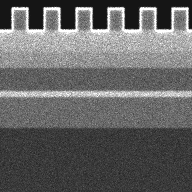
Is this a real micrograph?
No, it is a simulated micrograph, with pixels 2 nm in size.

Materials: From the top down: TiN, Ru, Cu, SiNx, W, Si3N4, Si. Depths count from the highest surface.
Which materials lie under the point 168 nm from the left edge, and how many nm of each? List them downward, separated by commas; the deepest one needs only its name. TiN 44, Ru 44, Cu 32, SiNx 46, W 12, Si3N4 62, Si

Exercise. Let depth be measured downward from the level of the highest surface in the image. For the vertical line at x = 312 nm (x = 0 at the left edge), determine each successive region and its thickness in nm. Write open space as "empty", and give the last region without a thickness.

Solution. empty 44, Ru 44, Cu 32, SiNx 46, W 12, Si3N4 62, Si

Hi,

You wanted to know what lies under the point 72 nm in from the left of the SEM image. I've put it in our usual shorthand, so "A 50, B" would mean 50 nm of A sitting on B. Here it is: empty 44, Ru 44, Cu 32, SiNx 46, W 12, Si3N4 62, Si